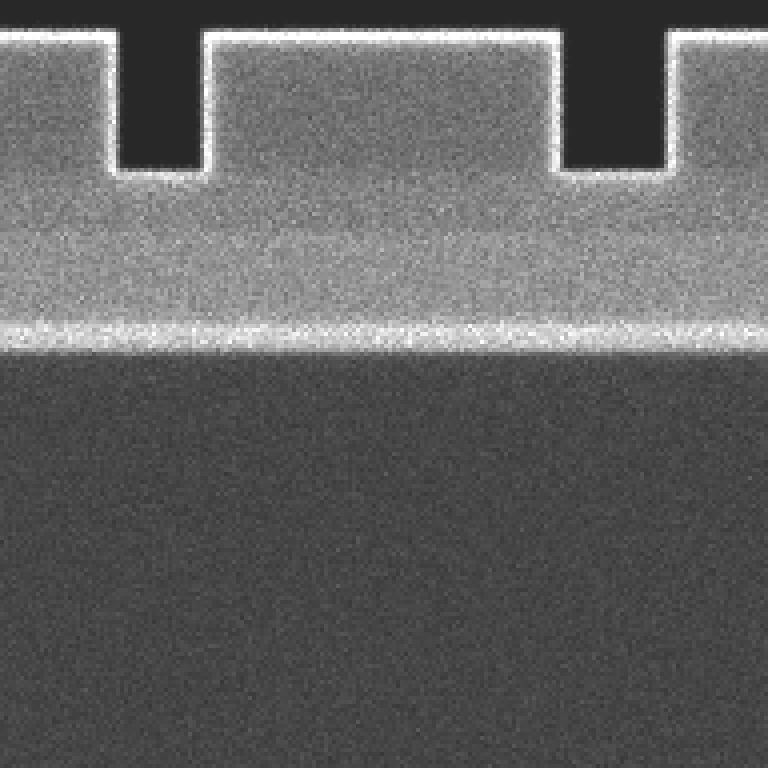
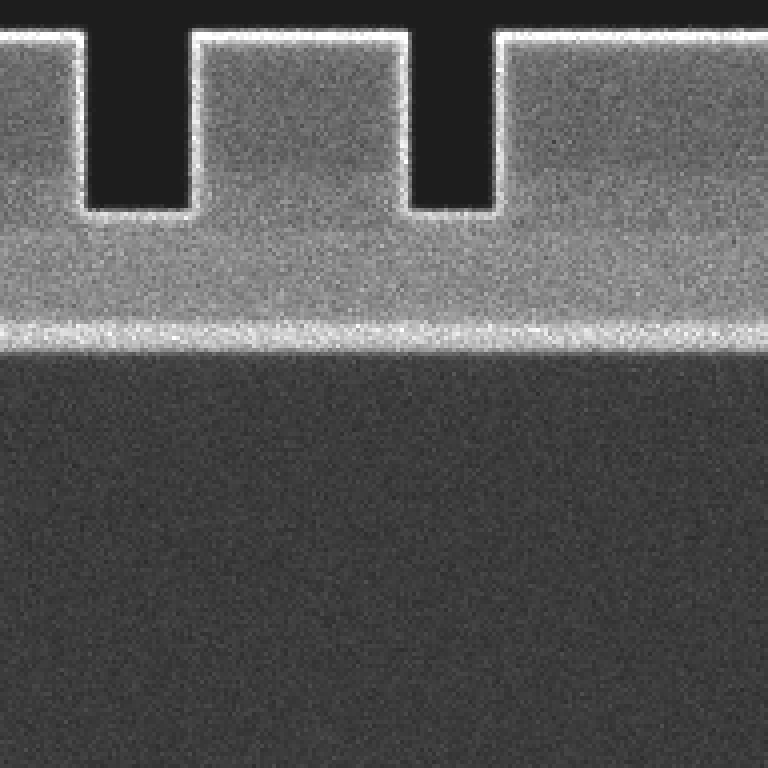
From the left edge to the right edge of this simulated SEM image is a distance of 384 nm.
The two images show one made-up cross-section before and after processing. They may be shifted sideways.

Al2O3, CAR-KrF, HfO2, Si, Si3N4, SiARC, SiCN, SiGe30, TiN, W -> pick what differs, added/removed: TiN removed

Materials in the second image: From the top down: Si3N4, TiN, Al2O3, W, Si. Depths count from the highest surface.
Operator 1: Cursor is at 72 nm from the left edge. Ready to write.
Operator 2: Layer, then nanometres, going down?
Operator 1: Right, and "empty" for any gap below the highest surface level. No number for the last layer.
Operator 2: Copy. empty 90, TiN 10, Al2O3 46, W 14, Si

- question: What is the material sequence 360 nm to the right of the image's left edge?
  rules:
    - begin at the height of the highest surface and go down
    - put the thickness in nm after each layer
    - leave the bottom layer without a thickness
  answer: Si3N4 70, TiN 30, Al2O3 46, W 14, Si